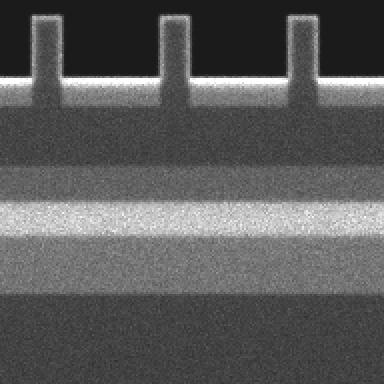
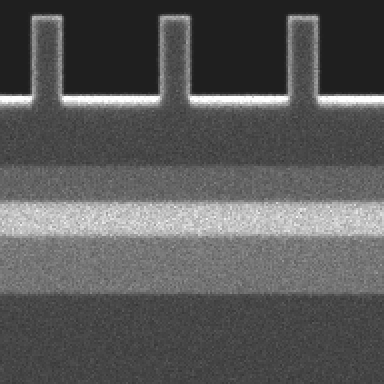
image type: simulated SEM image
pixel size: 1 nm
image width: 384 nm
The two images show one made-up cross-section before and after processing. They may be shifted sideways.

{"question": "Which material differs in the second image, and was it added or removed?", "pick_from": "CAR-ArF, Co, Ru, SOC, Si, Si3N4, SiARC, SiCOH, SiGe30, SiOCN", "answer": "SOC, removed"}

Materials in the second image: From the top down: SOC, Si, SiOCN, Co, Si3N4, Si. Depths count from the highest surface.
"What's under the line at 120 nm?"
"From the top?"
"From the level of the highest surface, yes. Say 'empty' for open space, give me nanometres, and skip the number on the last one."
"empty 80, SOC 10, Si 60, SiOCN 36, Co 34, Si3N4 58, Si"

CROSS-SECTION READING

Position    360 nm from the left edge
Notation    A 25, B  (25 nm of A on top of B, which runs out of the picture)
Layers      empty 80, SOC 10, Si 60, SiOCN 36, Co 34, Si3N4 58, Si